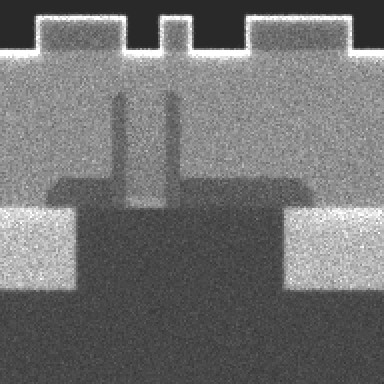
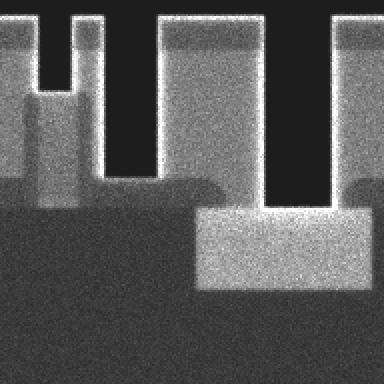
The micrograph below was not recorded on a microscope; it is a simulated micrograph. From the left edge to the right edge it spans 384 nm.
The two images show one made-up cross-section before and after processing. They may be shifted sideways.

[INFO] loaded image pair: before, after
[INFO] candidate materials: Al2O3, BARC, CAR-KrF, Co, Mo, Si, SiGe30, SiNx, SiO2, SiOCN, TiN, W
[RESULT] removed SiO2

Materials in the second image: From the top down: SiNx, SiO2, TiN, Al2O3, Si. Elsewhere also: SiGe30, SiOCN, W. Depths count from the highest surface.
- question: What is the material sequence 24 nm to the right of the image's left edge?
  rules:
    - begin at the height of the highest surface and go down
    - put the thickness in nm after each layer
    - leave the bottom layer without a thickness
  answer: SiNx 34, SiO2 48, SiOCN 110, Si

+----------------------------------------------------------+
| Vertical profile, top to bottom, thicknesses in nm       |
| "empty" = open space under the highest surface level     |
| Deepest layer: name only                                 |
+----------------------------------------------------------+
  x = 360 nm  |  SiNx 34, SiO2 128, SiGe30 30, W 82, Si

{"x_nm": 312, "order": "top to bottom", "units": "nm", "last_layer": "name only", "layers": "empty 192, W 82, Si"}